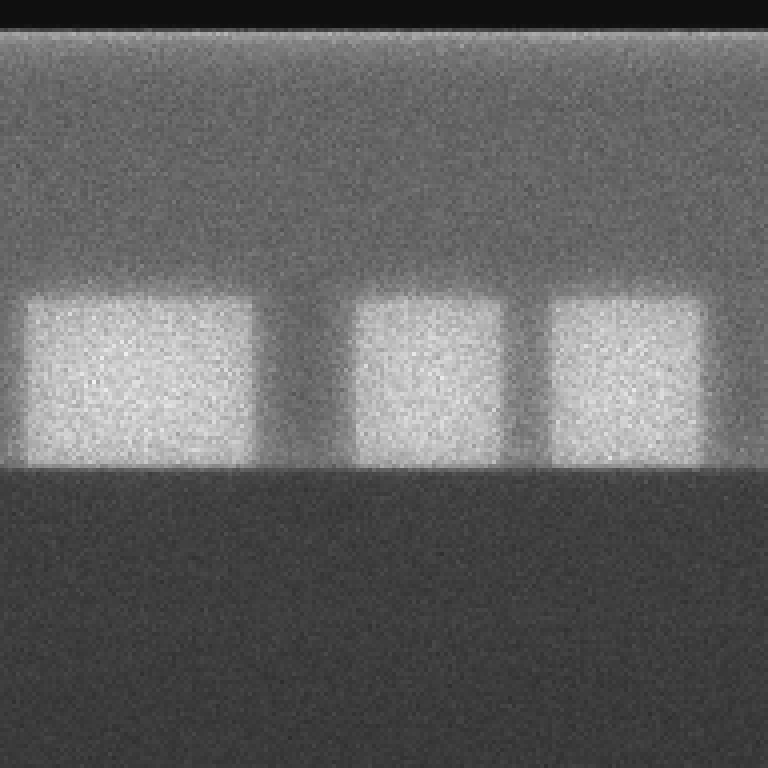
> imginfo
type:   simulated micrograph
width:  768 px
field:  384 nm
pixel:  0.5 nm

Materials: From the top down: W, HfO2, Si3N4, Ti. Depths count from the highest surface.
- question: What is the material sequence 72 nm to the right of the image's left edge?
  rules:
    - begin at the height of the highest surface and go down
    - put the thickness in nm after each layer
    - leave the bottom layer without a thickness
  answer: W 134, HfO2 84, Si3N4 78, Ti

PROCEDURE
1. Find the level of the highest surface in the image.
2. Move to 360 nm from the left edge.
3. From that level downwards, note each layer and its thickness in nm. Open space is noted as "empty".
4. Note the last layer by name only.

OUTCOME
W 218, Si3N4 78, Ti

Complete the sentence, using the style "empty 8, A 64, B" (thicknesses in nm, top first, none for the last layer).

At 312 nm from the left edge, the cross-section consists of W 134, HfO2 84, Si3N4 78, Ti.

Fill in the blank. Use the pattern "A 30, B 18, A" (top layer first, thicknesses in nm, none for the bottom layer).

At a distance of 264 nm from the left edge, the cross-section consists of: W 218, Si3N4 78, Ti